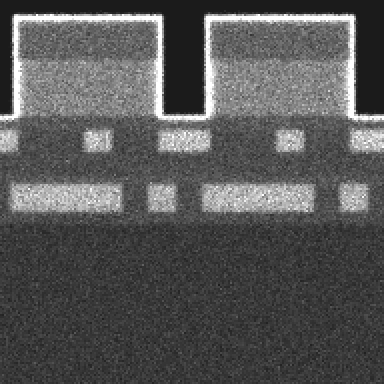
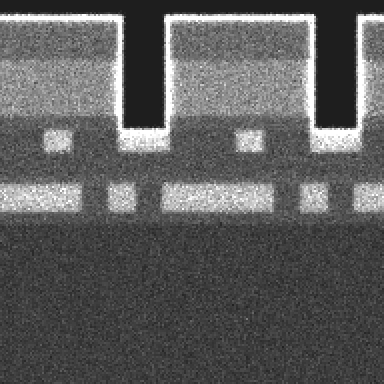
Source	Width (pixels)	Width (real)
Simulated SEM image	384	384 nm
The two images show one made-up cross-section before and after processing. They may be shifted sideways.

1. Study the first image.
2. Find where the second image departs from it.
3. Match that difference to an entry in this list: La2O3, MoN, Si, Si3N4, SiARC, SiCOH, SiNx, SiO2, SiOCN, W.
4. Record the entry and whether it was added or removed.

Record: SiNx / removed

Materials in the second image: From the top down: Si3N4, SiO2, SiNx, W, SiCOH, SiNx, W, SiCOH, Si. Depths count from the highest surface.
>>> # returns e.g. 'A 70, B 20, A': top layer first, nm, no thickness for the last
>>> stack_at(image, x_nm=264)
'Si3N4 44, SiO2 56, SiNx 14, SiCOH 46, SiNx 8, W 28, SiCOH 12, Si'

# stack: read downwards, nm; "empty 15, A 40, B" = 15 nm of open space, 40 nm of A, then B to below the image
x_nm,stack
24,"Si3N4 44, SiO2 56, SiNx 14, SiCOH 46, SiNx 8, W 28, SiCOH 12, Si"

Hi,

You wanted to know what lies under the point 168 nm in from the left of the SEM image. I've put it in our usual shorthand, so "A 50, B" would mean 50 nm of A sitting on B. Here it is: Si3N4 44, SiO2 56, SiNx 14, W 22, SiCOH 24, SiNx 8, W 28, SiCOH 12, Si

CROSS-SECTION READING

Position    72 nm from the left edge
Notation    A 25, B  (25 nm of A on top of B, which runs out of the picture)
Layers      Si3N4 44, SiO2 56, SiNx 14, SiCOH 46, SiNx 8, W 28, SiCOH 12, Si